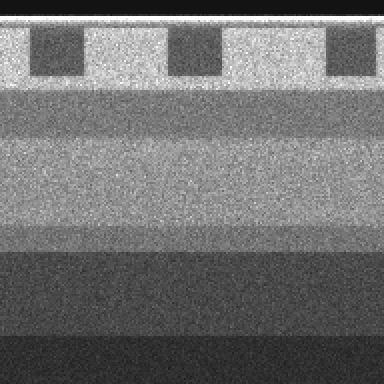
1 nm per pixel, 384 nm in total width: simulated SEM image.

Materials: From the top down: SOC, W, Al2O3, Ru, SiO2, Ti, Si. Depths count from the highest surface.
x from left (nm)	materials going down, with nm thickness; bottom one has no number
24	SOC 12, W 62, Al2O3 48, Ru 88, SiO2 26, Ti 84, Si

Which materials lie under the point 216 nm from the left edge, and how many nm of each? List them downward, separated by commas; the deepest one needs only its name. SOC 60, W 14, Al2O3 48, Ru 88, SiO2 26, Ti 84, Si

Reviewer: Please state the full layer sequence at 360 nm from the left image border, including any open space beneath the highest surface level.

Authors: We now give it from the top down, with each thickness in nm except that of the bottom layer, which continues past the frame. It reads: SOC 60, W 14, Al2O3 48, Ru 88, SiO2 26, Ti 84, Si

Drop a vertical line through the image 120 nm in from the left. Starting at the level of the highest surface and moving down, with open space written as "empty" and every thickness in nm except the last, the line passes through SOC 12, W 62, Al2O3 48, Ru 88, SiO2 26, Ti 84, Si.